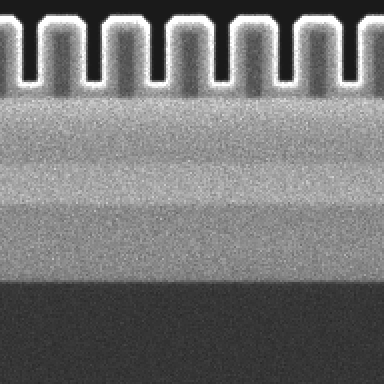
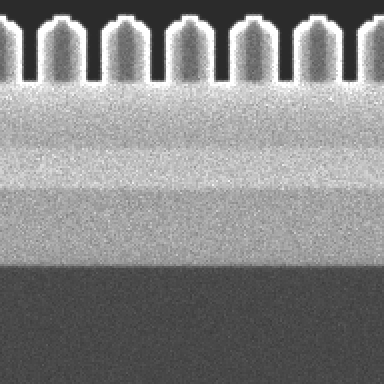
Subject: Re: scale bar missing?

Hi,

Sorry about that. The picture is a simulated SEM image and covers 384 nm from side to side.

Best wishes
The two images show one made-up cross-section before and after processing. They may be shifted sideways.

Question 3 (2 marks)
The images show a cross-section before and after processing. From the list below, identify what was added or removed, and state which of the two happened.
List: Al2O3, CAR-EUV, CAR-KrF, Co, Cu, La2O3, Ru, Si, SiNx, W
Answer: Al2O3 was removed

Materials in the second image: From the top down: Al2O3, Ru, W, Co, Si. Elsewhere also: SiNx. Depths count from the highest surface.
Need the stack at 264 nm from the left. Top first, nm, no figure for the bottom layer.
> empty 6, Al2O3 60, Ru 66, W 40, Co 78, Si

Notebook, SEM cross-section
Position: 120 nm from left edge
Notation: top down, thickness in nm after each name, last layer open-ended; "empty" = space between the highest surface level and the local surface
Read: SiNx 66, Ru 66, W 40, Co 78, Si